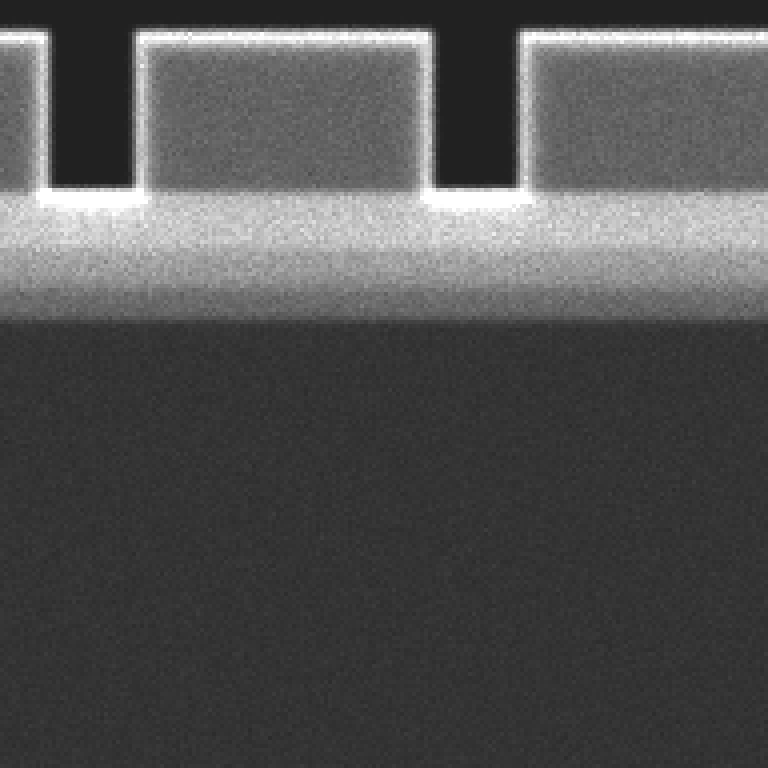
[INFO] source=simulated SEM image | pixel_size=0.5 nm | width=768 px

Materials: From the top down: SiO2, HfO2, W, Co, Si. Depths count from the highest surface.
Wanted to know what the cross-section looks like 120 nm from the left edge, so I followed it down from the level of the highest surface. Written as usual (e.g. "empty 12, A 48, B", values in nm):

SiO2 80, HfO2 28, W 20, Co 16, Si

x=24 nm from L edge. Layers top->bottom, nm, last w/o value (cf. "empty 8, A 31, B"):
empty 80, HfO2 28, W 20, Co 16, Si